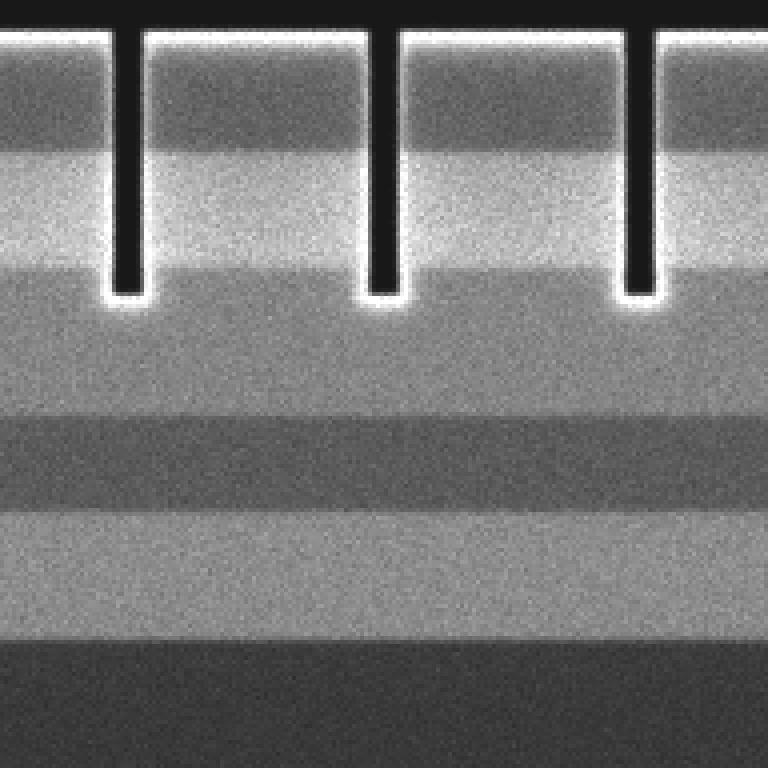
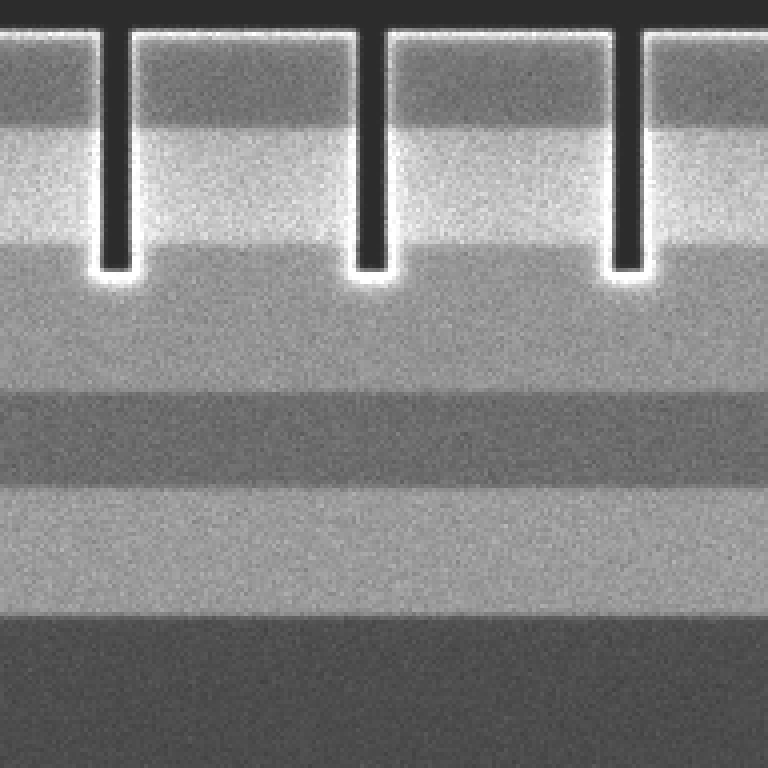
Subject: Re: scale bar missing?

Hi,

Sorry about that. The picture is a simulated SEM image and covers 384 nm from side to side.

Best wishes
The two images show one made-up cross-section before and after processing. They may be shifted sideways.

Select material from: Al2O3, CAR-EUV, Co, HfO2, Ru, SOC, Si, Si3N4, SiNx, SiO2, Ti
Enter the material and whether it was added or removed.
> SOC / removed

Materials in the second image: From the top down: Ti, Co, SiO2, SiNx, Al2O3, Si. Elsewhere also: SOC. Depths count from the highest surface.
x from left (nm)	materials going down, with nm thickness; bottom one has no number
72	Ti 48, Co 58, SiO2 74, SiNx 48, Al2O3 64, Si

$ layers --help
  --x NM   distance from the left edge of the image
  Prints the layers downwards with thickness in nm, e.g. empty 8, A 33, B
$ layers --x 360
Ti 48, Co 58, SiO2 74, SiNx 48, Al2O3 64, Si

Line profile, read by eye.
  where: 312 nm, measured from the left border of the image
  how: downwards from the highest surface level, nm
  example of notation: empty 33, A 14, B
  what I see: empty 120, SiO2 60, SiNx 48, Al2O3 64, Si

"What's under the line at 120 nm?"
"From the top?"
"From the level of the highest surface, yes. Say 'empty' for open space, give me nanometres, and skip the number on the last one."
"Ti 48, Co 58, SiO2 74, SiNx 48, Al2O3 64, Si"